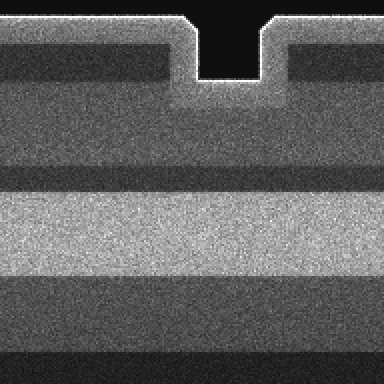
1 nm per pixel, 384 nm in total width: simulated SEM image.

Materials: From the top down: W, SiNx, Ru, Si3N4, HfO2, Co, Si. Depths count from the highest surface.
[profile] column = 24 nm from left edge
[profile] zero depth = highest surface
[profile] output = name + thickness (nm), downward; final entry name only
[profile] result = W 28, SiNx 38, Ru 84, Si3N4 26, HfO2 84, Co 76, Si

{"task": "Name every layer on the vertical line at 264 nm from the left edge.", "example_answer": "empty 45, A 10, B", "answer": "empty 10, W 82, Ru 58, Si3N4 26, HfO2 84, Co 76, Si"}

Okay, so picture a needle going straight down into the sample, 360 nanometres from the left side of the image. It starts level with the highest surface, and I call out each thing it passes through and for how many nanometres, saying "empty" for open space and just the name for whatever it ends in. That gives W 28, SiNx 38, Ru 84, Si3N4 26, HfO2 84, Co 76, Si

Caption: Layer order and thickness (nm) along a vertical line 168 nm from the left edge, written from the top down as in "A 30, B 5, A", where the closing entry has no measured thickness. W 28, SiNx 38, Ru 84, Si3N4 26, HfO2 84, Co 76, Si